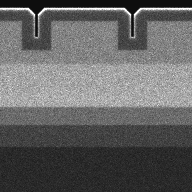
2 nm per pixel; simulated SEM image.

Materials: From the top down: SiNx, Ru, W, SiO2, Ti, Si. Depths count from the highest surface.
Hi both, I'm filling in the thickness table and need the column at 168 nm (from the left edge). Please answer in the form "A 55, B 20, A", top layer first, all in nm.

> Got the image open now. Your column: SiNx 26, Ru 86, W 86, SiO2 36, Ti 44, Si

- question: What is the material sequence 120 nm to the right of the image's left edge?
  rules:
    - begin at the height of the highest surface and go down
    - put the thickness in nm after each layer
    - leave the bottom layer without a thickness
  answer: SiNx 26, Ru 86, W 86, SiO2 36, Ti 44, Si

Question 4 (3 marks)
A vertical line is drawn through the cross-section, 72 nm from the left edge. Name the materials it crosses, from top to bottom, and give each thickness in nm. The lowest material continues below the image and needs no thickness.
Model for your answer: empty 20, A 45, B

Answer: empty 58, SiNx 26, Ru 28, W 86, SiO2 36, Ti 44, Si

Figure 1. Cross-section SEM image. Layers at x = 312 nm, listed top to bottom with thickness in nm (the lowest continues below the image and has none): SiNx 26, Ru 86, W 86, SiO2 36, Ti 44, Si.